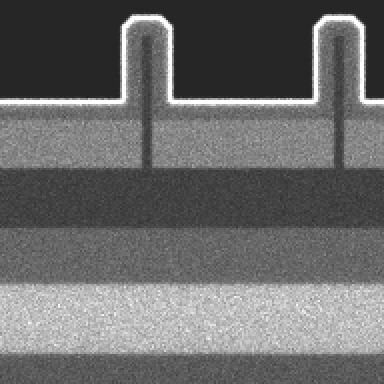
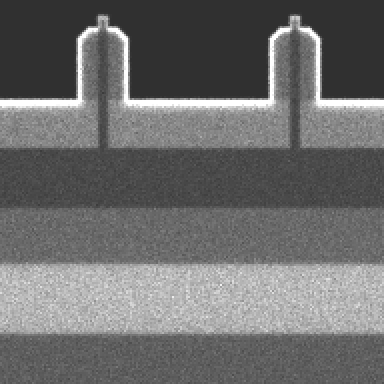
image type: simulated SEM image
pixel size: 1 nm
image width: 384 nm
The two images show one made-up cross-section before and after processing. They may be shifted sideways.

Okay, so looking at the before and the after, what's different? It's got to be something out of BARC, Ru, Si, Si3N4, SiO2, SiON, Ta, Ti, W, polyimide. Si3N4, removed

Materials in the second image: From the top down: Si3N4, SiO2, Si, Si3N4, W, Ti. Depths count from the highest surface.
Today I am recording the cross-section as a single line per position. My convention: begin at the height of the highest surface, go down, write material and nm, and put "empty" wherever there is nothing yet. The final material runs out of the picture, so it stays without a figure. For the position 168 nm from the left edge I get empty 84, SiO2 48, Si 60, Si3N4 56, W 70, Ti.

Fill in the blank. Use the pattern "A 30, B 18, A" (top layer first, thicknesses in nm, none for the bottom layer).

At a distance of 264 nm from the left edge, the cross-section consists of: empty 84, SiO2 48, Si 60, Si3N4 56, W 70, Ti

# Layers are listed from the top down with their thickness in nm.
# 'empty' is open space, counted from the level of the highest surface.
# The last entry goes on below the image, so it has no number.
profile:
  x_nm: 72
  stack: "empty 84, SiO2 48, Si 60, Si3N4 56, W 70, Ti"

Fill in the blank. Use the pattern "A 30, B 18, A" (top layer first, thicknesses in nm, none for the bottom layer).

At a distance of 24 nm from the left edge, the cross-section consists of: empty 84, SiO2 48, Si 60, Si3N4 56, W 70, Ti